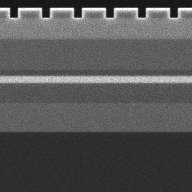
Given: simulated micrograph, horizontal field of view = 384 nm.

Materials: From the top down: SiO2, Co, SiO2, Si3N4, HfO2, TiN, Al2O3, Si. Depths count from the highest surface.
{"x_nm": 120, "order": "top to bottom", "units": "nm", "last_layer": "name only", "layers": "SiO2 20, Co 42, SiO2 62, Si3N4 12, HfO2 14, TiN 40, Al2O3 58, Si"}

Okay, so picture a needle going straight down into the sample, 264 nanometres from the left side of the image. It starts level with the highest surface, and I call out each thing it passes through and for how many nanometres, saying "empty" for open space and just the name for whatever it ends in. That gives SiO2 20, Co 42, SiO2 62, Si3N4 12, HfO2 14, TiN 40, Al2O3 58, Si